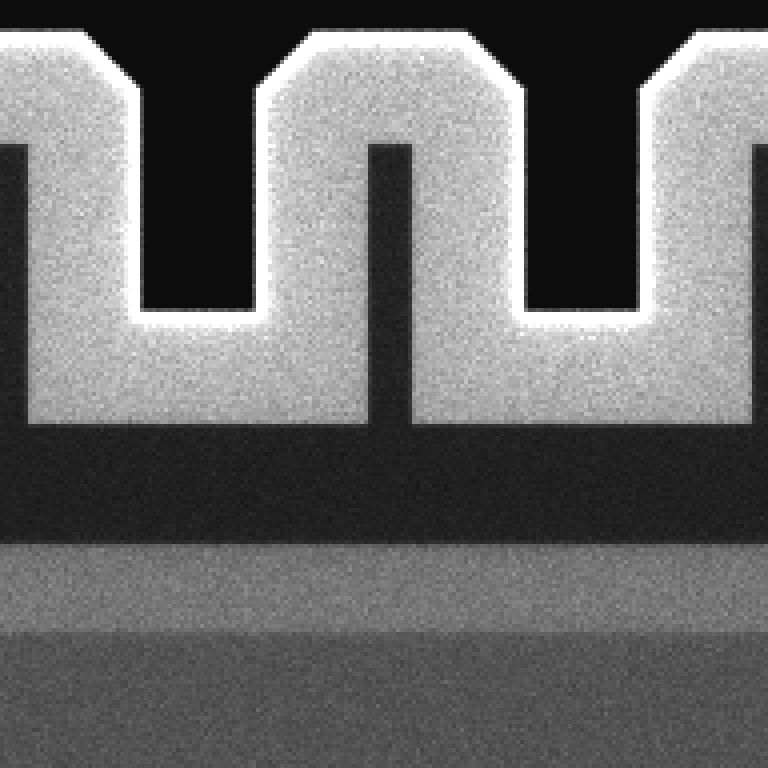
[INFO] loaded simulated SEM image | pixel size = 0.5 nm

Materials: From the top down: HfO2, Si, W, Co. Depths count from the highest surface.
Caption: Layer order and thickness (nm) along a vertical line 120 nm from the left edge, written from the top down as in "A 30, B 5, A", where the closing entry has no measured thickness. empty 140, HfO2 56, Si 60, W 44, Co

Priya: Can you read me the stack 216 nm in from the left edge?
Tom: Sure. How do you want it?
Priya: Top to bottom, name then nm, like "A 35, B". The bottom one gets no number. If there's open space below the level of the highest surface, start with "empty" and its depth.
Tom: HfO2 196, Si 60, W 44, Co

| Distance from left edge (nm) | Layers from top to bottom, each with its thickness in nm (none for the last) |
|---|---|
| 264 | empty 140, HfO2 56, Si 60, W 44, Co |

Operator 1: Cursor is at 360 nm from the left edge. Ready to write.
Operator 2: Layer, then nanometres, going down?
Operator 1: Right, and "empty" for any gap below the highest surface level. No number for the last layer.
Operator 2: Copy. HfO2 196, Si 60, W 44, Co